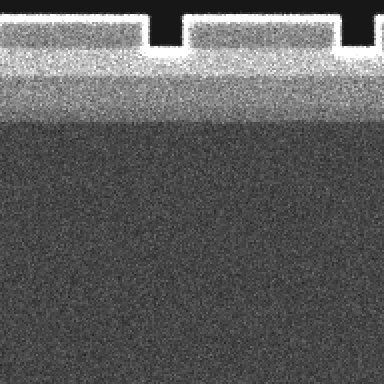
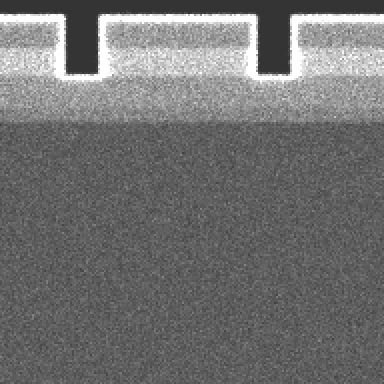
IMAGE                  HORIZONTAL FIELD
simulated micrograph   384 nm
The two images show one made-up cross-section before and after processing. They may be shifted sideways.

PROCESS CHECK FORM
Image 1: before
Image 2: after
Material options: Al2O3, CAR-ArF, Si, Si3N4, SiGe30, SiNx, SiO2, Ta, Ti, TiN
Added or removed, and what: removed, Al2O3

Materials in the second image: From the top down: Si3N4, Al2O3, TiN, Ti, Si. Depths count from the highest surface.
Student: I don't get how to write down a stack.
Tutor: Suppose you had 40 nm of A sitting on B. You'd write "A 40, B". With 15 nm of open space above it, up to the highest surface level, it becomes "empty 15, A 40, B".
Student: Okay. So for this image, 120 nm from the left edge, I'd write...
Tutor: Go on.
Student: Si3N4 32, Al2O3 28, TiN 32, Ti 14, Si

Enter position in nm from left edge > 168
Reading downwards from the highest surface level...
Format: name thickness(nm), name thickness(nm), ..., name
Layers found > Si3N4 32, Al2O3 28, TiN 32, Ti 14, Si